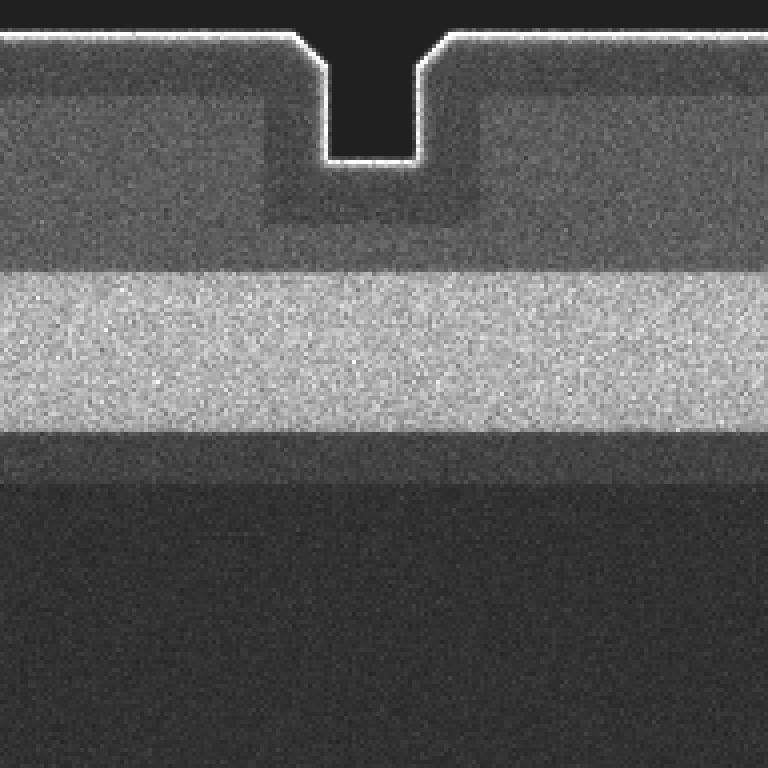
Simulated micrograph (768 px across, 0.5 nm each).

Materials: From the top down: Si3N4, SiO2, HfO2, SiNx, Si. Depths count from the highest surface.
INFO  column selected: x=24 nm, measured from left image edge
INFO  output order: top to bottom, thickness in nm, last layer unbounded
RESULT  Si3N4 32, SiO2 88, HfO2 80, SiNx 26, Si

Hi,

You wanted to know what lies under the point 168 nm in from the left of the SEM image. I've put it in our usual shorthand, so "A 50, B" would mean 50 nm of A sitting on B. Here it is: empty 64, Si3N4 32, SiO2 24, HfO2 80, SiNx 26, Si